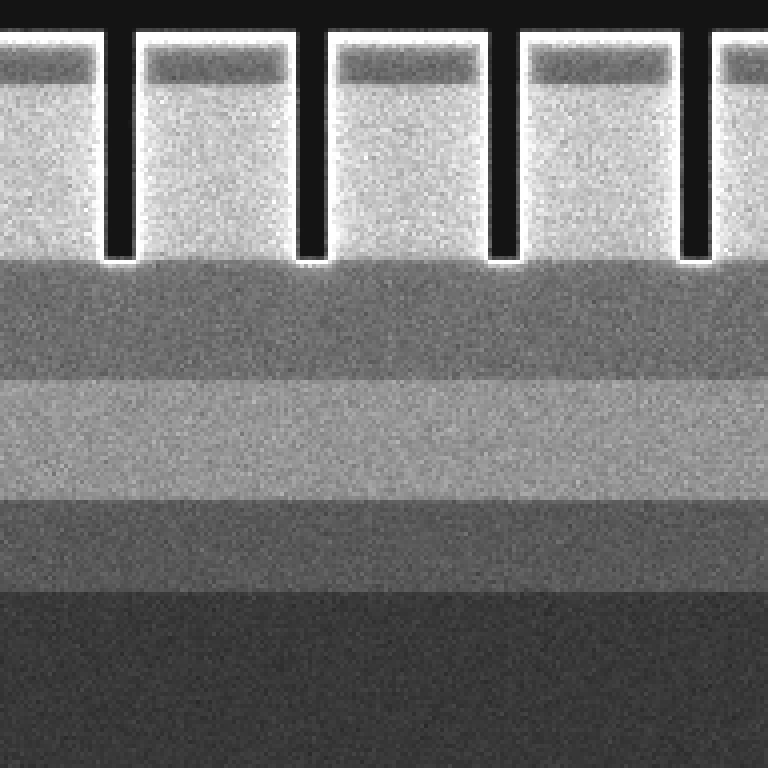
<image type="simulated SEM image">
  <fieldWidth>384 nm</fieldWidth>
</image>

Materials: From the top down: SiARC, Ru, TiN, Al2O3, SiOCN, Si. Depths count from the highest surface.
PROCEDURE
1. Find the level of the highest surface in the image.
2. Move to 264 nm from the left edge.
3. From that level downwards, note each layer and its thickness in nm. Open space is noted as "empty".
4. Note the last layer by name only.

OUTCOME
SiARC 26, Ru 88, TiN 60, Al2O3 60, SiOCN 46, Si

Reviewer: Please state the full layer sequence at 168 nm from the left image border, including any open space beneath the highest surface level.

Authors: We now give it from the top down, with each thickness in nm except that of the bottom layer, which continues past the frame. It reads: SiARC 26, Ru 88, TiN 60, Al2O3 60, SiOCN 46, Si